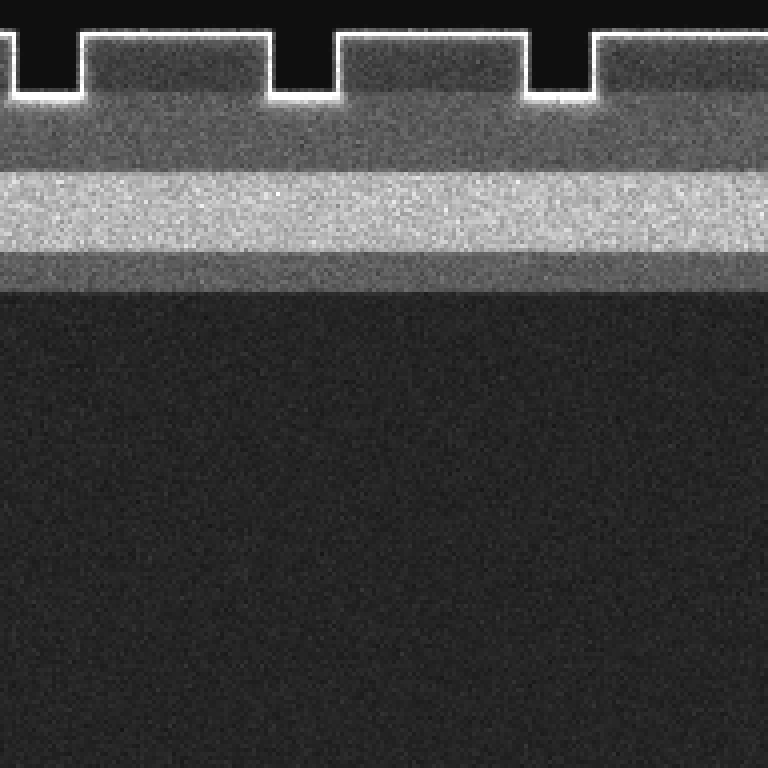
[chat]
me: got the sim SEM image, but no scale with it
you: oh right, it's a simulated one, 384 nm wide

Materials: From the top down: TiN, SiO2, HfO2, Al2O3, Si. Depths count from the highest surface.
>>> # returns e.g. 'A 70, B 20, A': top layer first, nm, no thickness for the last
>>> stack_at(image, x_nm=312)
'TiN 30, SiO2 40, HfO2 40, Al2O3 20, Si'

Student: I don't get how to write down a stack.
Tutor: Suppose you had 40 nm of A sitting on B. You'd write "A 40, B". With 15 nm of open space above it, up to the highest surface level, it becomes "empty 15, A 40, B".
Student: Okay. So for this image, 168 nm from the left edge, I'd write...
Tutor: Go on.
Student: TiN 30, SiO2 40, HfO2 40, Al2O3 20, Si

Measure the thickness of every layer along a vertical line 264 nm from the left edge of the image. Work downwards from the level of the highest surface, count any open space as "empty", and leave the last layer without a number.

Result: empty 30, SiO2 40, HfO2 40, Al2O3 20, Si